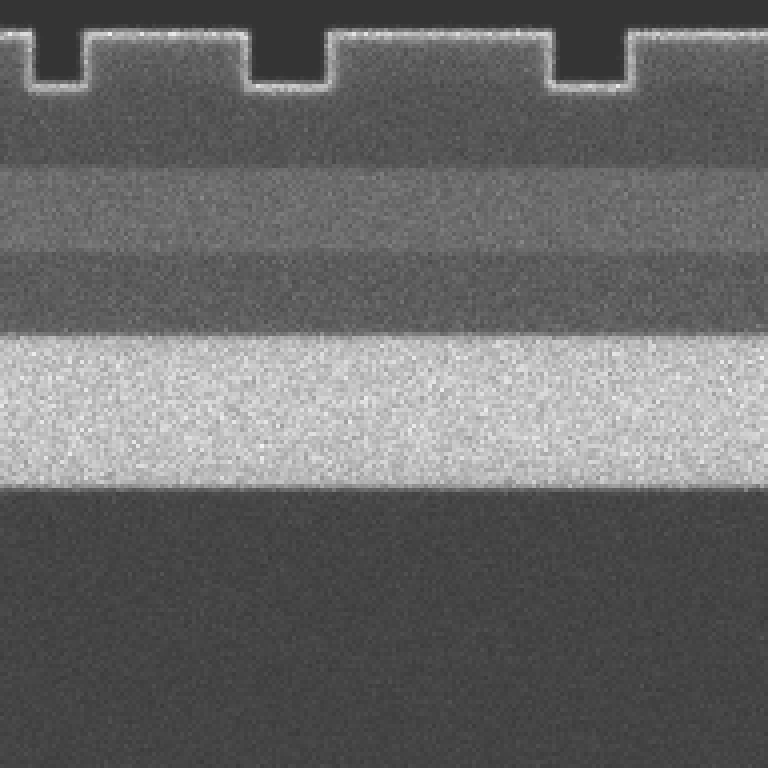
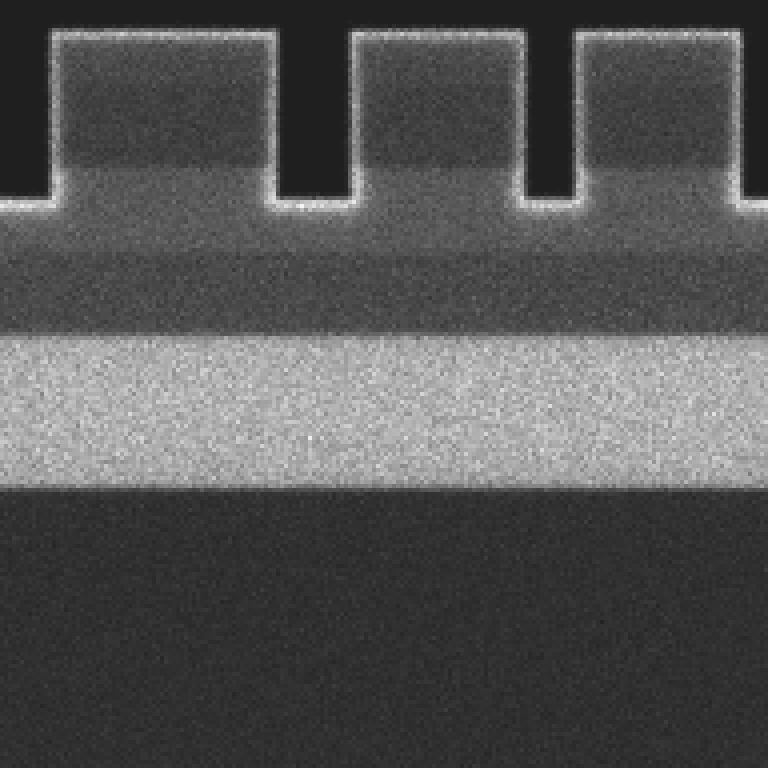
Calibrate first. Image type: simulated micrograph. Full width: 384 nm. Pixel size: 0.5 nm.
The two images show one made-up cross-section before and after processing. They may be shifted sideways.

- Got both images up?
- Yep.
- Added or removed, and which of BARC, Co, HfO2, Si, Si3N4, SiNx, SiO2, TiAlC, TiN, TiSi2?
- removed, SiNx and SiO2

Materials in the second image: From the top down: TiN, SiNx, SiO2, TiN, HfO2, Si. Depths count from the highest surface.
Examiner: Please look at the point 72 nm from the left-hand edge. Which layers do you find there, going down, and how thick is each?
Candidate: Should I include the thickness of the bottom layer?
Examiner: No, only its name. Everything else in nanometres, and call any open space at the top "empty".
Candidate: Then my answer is TiN 26, SiNx 42, SiO2 42, TiN 42, HfO2 76, Si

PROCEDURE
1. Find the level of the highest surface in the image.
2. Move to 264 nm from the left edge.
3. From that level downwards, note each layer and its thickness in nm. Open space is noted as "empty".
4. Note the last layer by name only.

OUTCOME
empty 84, SiO2 26, TiN 42, HfO2 76, Si